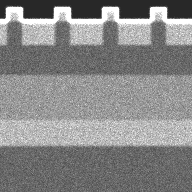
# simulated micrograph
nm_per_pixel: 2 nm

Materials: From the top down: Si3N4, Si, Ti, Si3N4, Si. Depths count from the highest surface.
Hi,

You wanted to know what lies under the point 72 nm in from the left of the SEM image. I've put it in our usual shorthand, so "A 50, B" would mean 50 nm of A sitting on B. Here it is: empty 24, Si3N4 50, Si 60, Ti 90, Si3N4 52, Si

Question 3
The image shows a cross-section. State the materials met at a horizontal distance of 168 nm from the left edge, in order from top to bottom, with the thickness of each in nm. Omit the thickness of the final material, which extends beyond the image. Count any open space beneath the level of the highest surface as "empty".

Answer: empty 24, Si3N4 50, Si 60, Ti 90, Si3N4 52, Si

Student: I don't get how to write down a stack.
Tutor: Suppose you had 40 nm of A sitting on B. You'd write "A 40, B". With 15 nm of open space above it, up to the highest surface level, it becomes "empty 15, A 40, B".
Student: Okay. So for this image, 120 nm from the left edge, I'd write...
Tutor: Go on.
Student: Si3N4 26, Si 108, Ti 90, Si3N4 52, Si